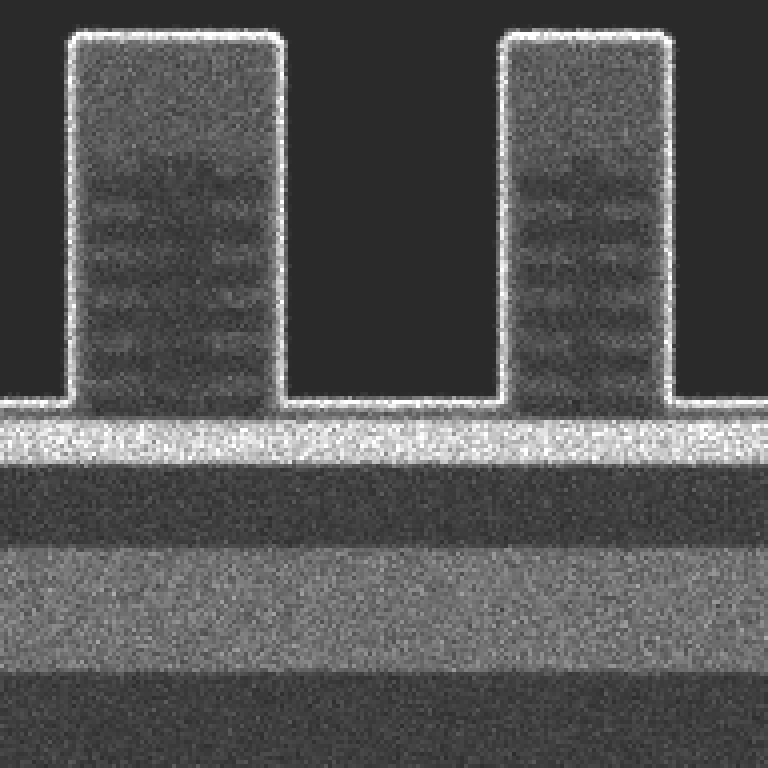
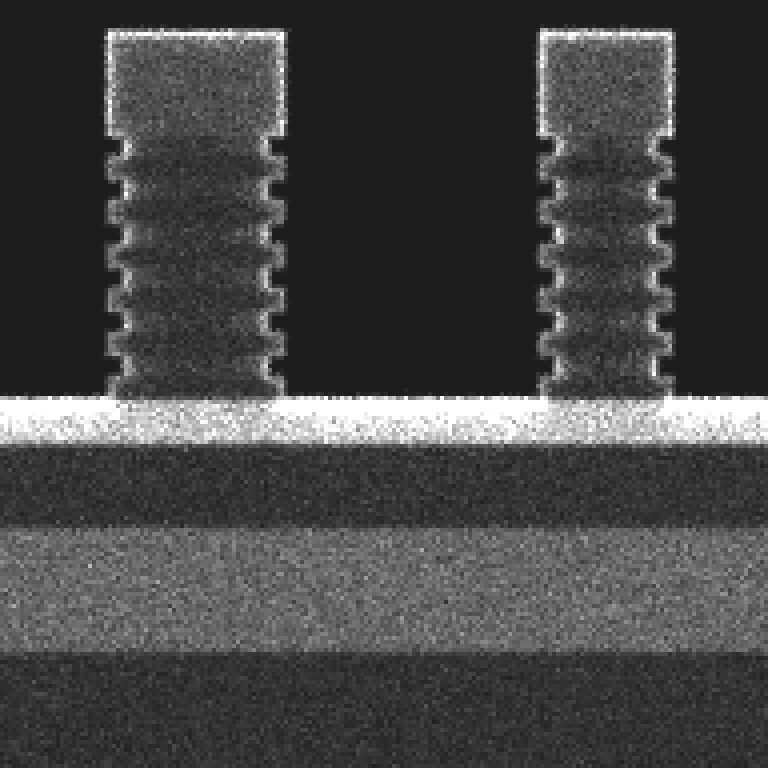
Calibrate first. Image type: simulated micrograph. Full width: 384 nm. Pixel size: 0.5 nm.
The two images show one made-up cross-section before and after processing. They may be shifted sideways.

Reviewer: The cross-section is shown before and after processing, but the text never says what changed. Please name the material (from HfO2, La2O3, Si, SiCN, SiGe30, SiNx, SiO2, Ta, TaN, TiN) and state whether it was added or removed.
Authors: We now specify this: SiNx, removed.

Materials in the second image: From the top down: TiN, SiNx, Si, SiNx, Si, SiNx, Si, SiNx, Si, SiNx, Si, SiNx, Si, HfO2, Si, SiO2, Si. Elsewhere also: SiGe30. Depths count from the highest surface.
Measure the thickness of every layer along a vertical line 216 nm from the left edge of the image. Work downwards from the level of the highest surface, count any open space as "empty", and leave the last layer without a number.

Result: empty 184, HfO2 22, Si 42, SiO2 62, Si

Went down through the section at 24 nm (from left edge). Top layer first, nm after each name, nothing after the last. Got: empty 184, HfO2 22, Si 42, SiO2 62, Si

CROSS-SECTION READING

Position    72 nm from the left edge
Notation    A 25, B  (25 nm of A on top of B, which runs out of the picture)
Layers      TiN 52, SiNx 10, Si 12, SiNx 10, Si 12, SiNx 10, Si 12, SiNx 10, Si 12, SiNx 10, Si 12, SiNx 10, Si 12, HfO2 22, Si 42, SiO2 62, Si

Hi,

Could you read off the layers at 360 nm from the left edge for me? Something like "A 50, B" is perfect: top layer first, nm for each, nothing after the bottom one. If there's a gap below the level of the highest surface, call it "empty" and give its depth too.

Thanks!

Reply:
empty 184, HfO2 22, Si 42, SiO2 62, Si